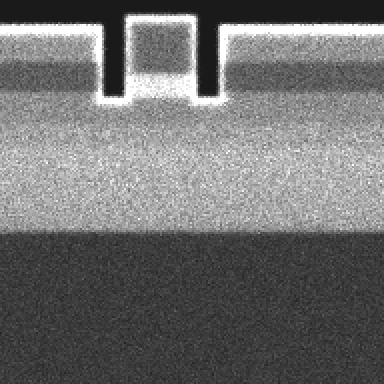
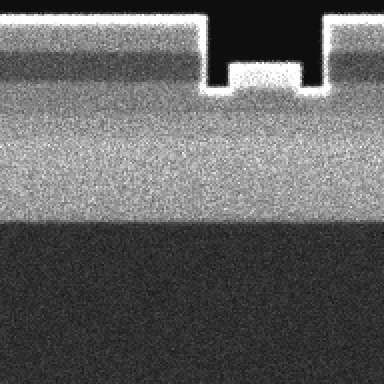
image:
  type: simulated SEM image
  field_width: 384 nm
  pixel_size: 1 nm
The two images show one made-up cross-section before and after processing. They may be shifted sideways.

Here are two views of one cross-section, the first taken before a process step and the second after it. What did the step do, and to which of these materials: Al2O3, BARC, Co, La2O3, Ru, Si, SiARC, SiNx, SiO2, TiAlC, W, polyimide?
It removed SiARC.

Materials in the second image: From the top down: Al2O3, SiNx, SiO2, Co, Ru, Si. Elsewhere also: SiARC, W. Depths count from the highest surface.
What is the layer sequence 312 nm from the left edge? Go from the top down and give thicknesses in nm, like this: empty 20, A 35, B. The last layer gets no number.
empty 72, SiO2 26, Co 24, Ru 84, Si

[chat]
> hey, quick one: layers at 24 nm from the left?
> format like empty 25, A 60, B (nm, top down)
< Al2O3 36, SiNx 30, SiO2 32, Co 24, Ru 84, Si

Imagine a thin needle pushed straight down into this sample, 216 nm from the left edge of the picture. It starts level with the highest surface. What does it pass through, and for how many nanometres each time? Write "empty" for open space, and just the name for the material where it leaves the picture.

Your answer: empty 72, SiO2 26, Co 24, Ru 84, Si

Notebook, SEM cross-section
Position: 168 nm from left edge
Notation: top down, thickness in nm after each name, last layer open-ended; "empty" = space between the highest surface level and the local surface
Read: Al2O3 36, SiNx 30, SiO2 32, Co 24, Ru 84, Si